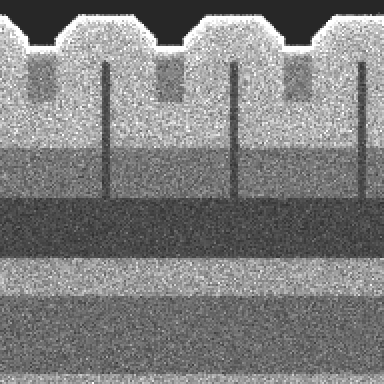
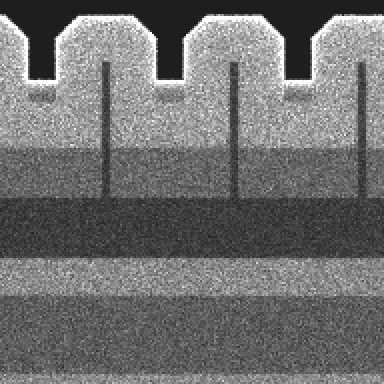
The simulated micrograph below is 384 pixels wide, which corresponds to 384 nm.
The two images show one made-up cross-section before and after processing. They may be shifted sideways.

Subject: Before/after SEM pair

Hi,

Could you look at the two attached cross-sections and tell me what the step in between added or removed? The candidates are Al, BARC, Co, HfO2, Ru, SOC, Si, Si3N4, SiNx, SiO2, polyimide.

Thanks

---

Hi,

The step removed SOC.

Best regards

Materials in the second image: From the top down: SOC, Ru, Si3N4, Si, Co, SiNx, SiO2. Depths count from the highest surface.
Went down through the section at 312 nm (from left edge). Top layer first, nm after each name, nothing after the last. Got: empty 22, Ru 110, Si3N4 50, Si 60, Co 38, SiNx 78, SiO2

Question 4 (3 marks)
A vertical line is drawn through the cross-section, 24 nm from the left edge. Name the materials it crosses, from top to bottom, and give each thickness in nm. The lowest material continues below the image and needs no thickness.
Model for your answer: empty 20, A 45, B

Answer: empty 20, Ru 112, Si3N4 50, Si 60, Co 38, SiNx 78, SiO2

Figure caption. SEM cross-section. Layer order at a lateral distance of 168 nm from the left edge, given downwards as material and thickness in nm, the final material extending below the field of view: empty 64, SOC 22, Ru 46, Si3N4 50, Si 60, Co 38, SiNx 78, SiO2